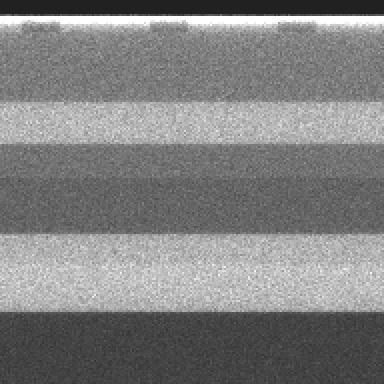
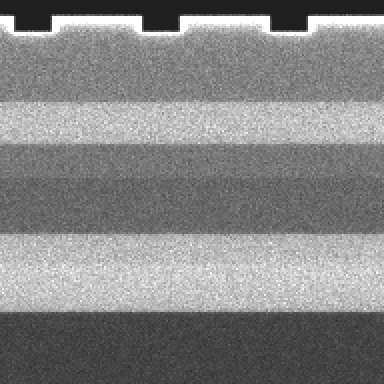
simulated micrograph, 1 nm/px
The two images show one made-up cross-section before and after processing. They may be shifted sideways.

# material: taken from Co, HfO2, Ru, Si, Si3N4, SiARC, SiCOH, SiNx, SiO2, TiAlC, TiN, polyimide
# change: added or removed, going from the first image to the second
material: SiARC
change: removed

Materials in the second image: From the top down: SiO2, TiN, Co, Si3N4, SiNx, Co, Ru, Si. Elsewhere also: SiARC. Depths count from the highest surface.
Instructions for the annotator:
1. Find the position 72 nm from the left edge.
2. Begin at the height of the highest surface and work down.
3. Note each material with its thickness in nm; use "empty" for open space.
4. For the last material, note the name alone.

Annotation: SiO2 16, TiN 70, Co 42, Si3N4 34, SiNx 56, Co 30, Ru 48, Si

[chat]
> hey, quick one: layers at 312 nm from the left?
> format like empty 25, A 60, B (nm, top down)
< SiO2 16, TiN 70, Co 42, Si3N4 34, SiNx 56, Co 30, Ru 48, Si